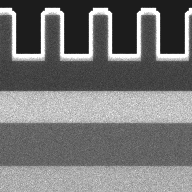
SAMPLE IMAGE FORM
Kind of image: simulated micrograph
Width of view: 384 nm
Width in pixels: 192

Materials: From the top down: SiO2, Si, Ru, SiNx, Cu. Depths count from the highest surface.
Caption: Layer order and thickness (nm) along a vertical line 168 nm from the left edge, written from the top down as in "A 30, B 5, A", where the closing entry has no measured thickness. empty 92, SiO2 14, Si 60, Ru 64, SiNx 86, Cu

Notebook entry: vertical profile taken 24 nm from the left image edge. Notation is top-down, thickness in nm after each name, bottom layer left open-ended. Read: empty 6, SiO2 100, Si 60, Ru 64, SiNx 86, Cu